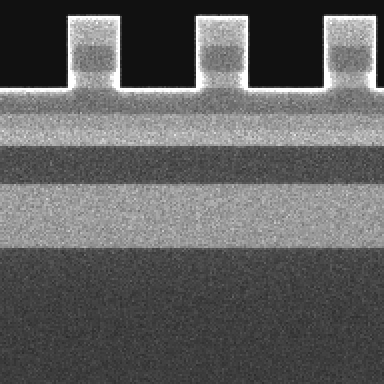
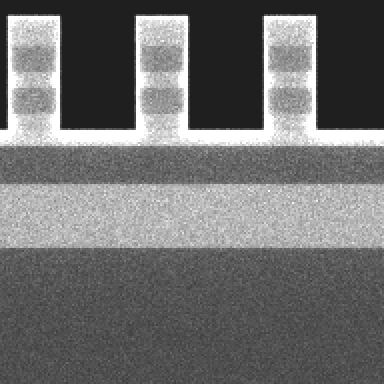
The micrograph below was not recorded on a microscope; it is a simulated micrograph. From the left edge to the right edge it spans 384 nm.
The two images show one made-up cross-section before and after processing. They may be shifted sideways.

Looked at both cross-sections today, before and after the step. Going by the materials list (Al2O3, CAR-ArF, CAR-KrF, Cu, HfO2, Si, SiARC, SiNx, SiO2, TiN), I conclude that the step removed SiNx and SiO2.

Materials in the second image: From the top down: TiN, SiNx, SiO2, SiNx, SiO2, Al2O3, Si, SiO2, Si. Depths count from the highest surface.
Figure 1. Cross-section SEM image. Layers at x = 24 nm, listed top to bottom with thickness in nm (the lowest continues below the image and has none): TiN 30, SiNx 26, SiO2 16, SiNx 26, SiO2 16, Al2O3 16, Si 38, SiO2 64, Si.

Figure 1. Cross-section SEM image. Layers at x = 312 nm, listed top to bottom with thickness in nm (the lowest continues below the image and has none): TiN 30, SiNx 26, SiO2 16, SiNx 26, SiO2 16, Al2O3 16, Si 38, SiO2 64, Si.